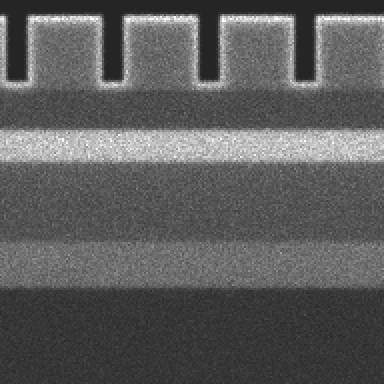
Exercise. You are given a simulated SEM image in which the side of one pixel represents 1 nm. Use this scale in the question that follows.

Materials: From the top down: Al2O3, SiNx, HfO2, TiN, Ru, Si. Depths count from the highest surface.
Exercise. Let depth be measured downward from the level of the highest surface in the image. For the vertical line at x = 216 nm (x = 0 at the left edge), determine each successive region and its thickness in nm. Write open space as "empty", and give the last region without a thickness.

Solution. empty 66, Al2O3 8, SiNx 40, HfO2 32, TiN 80, Ru 46, Si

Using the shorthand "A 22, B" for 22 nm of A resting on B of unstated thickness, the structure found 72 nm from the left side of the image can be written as Al2O3 74, SiNx 40, HfO2 32, TiN 80, Ru 46, Si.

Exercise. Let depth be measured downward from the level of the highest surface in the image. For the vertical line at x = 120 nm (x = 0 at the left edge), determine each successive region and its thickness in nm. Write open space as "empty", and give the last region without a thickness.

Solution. empty 66, Al2O3 8, SiNx 40, HfO2 32, TiN 80, Ru 46, Si